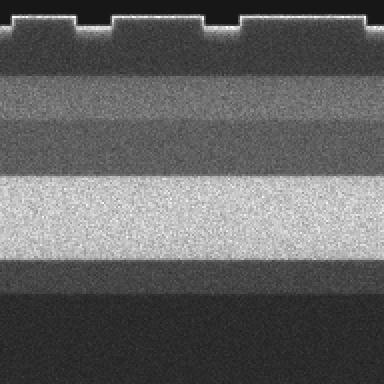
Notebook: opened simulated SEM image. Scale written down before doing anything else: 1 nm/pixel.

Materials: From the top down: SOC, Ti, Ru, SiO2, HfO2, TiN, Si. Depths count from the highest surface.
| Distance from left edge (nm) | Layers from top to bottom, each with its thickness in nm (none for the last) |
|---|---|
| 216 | empty 10, SOC 14, Ti 36, Ru 44, SiO2 56, HfO2 84, TiN 34, Si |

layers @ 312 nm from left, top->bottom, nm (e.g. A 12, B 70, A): Ti 60, Ru 44, SiO2 56, HfO2 84, TiN 34, Si